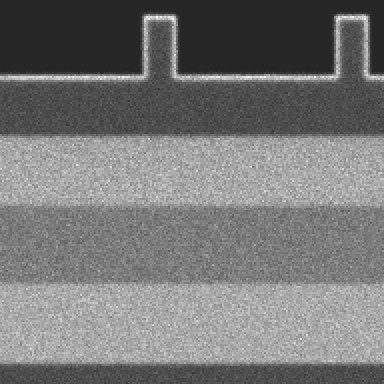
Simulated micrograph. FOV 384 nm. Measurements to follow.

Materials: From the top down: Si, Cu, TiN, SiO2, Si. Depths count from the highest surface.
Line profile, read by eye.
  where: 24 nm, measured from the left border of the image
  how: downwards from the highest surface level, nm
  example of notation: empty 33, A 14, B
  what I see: empty 60, Si 60, Cu 70, TiN 78, SiO2 80, Si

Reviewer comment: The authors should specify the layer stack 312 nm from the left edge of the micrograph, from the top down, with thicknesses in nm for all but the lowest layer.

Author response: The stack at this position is empty 60, Si 60, Cu 70, TiN 78, SiO2 80, Si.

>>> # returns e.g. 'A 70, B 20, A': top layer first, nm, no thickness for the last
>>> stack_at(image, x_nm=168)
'Si 120, Cu 70, TiN 78, SiO2 80, Si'